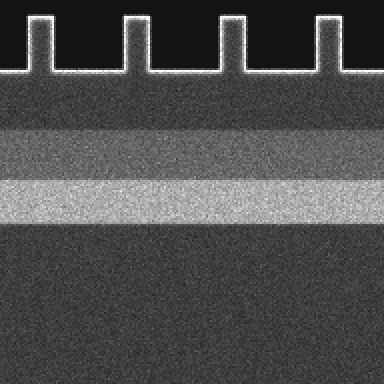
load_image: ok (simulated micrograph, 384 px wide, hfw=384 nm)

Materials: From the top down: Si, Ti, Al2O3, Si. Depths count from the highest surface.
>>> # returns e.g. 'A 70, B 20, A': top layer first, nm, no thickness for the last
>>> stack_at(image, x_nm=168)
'empty 54, Si 60, Ti 50, Al2O3 44, Si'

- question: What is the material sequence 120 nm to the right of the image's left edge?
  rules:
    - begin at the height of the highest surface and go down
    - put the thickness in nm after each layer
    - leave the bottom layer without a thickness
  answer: empty 54, Si 60, Ti 50, Al2O3 44, Si